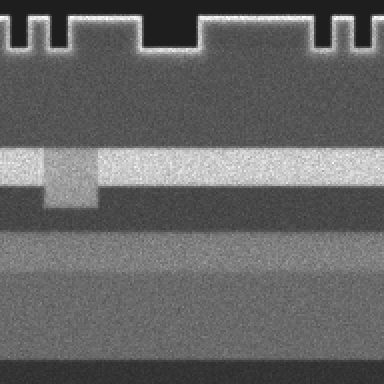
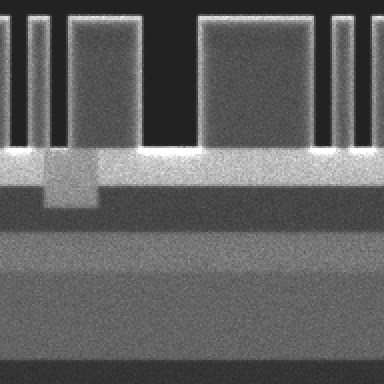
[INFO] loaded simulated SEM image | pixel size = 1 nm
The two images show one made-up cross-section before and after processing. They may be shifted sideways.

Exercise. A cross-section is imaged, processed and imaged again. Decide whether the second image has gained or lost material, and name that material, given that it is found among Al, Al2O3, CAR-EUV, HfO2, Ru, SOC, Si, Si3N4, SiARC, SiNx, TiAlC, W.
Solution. removed: SOC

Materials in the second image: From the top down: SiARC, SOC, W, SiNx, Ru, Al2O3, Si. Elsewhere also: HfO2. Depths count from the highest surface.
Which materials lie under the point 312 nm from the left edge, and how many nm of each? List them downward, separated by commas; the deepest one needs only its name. SiARC 32, SOC 100, HfO2 38, SiNx 46, Ru 40, Al2O3 88, Si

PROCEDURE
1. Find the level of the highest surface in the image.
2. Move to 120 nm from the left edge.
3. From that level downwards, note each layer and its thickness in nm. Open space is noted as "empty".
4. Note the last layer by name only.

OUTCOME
SiARC 32, SOC 100, HfO2 38, SiNx 46, Ru 40, Al2O3 88, Si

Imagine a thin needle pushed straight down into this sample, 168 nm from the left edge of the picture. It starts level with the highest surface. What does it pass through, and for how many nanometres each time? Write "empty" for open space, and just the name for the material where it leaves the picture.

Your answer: empty 132, HfO2 38, SiNx 46, Ru 40, Al2O3 88, Si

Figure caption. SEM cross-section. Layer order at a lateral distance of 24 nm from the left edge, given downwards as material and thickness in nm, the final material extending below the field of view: empty 132, HfO2 38, SiNx 46, Ru 40, Al2O3 88, Si